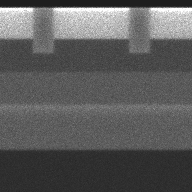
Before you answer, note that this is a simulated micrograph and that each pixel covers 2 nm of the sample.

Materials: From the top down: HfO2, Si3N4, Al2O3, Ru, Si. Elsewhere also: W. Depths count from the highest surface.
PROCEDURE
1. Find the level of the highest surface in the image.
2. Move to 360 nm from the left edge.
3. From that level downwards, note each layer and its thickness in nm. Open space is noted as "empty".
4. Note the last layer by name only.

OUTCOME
HfO2 62, Si3N4 66, Al2O3 66, Ru 90, Si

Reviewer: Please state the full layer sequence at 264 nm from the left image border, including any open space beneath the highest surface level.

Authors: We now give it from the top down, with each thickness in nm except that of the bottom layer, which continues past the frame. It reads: W 90, Si3N4 38, Al2O3 66, Ru 90, Si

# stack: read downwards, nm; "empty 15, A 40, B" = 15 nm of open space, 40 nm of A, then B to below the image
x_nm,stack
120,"HfO2 62, Si3N4 66, Al2O3 66, Ru 90, Si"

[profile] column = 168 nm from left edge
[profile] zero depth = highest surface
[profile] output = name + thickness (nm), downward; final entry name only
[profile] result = HfO2 62, Si3N4 66, Al2O3 66, Ru 90, Si